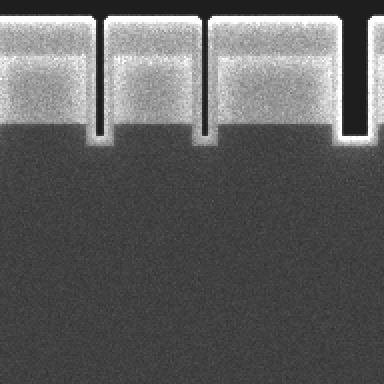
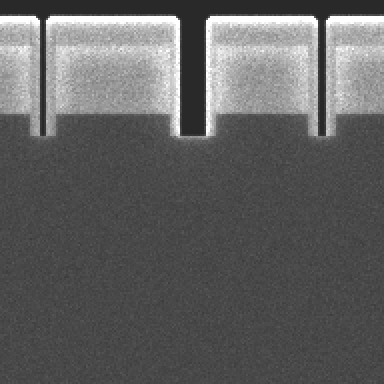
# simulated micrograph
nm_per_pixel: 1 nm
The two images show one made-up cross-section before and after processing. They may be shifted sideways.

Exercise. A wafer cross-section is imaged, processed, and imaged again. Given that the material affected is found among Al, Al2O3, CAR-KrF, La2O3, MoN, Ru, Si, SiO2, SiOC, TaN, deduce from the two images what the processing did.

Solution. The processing removed SiO2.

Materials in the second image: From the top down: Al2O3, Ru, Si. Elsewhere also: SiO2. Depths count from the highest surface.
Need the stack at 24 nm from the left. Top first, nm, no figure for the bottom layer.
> Al2O3 30, Ru 68, Si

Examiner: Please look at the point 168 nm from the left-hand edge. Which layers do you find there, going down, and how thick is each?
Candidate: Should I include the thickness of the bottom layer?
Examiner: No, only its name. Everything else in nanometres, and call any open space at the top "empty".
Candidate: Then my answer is Al2O3 30, Ru 68, Si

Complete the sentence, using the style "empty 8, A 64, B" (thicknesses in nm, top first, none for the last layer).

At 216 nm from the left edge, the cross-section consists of Al2O3 30, Ru 68, Si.